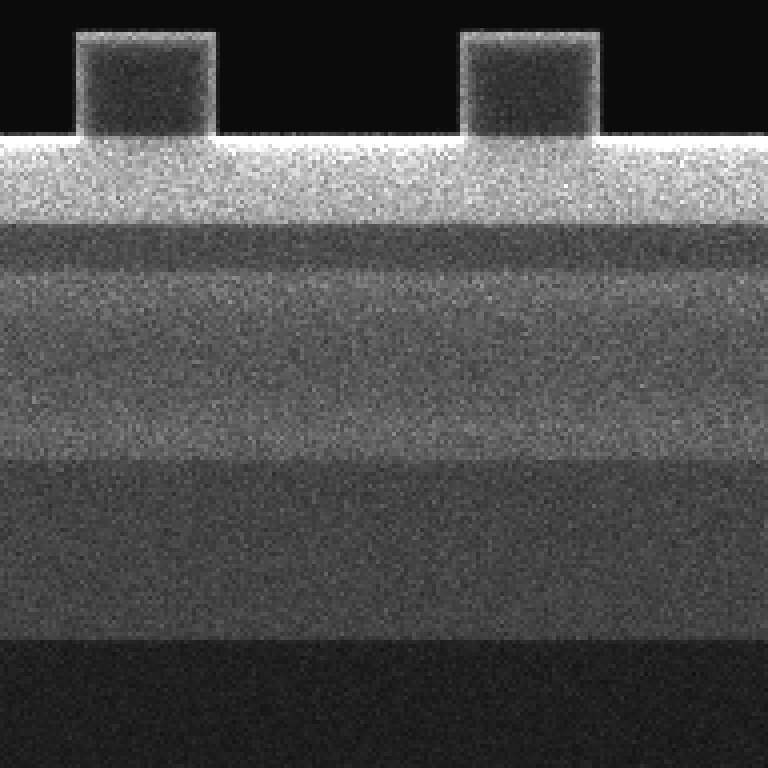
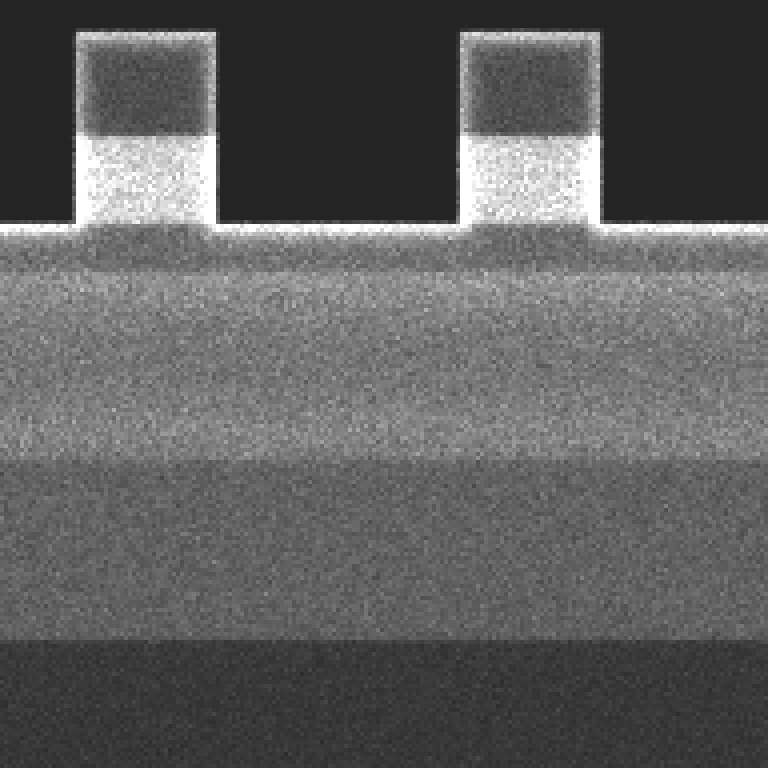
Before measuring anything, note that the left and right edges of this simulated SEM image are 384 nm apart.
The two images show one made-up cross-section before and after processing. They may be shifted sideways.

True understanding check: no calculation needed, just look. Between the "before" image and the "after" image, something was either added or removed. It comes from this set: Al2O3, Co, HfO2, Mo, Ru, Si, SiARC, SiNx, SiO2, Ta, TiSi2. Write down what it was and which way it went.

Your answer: HfO2 (removed)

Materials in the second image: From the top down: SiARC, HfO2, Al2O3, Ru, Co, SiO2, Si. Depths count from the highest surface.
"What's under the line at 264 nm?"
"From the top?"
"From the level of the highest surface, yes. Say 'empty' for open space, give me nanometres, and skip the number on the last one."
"SiARC 52, HfO2 44, Al2O3 24, Ru 82, Co 12, SiO2 90, Si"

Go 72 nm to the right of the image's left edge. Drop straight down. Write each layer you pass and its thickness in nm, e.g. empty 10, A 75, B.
SiARC 52, HfO2 44, Al2O3 24, Ru 82, Co 12, SiO2 90, Si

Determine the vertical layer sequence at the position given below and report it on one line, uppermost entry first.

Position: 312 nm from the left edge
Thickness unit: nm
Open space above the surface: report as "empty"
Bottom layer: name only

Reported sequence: empty 96, Al2O3 24, Ru 82, Co 12, SiO2 90, Si